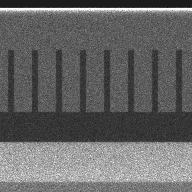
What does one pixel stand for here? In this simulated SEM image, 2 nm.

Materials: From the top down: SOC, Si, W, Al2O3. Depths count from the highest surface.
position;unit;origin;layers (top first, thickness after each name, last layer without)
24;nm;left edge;SOC 84, Si 184, W 80, Al2O3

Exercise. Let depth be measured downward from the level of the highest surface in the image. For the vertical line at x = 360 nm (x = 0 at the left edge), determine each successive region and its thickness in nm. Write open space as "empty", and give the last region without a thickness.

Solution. SOC 84, Si 184, W 80, Al2O3